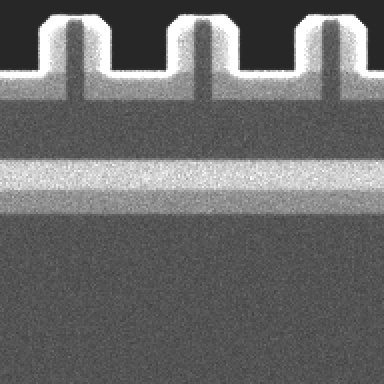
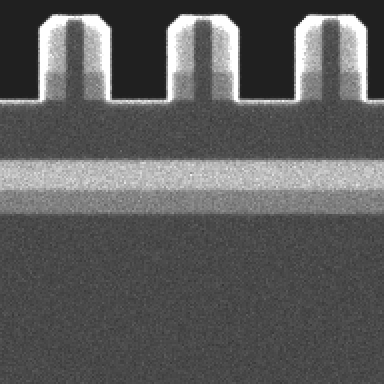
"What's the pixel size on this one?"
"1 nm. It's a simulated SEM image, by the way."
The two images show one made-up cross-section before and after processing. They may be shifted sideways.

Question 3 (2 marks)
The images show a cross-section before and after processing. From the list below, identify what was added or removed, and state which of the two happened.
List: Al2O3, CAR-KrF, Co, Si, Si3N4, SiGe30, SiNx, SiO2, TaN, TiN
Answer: Si3N4 was removed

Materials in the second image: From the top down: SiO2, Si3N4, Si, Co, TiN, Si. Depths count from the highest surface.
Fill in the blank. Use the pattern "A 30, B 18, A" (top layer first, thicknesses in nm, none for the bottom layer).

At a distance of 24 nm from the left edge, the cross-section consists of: empty 84, Si 60, Co 30, TiN 24, Si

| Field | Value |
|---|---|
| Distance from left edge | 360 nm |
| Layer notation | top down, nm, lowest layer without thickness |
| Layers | empty 8, SiO2 48, Si3N4 28, Si 60, Co 30, TiN 24, Si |